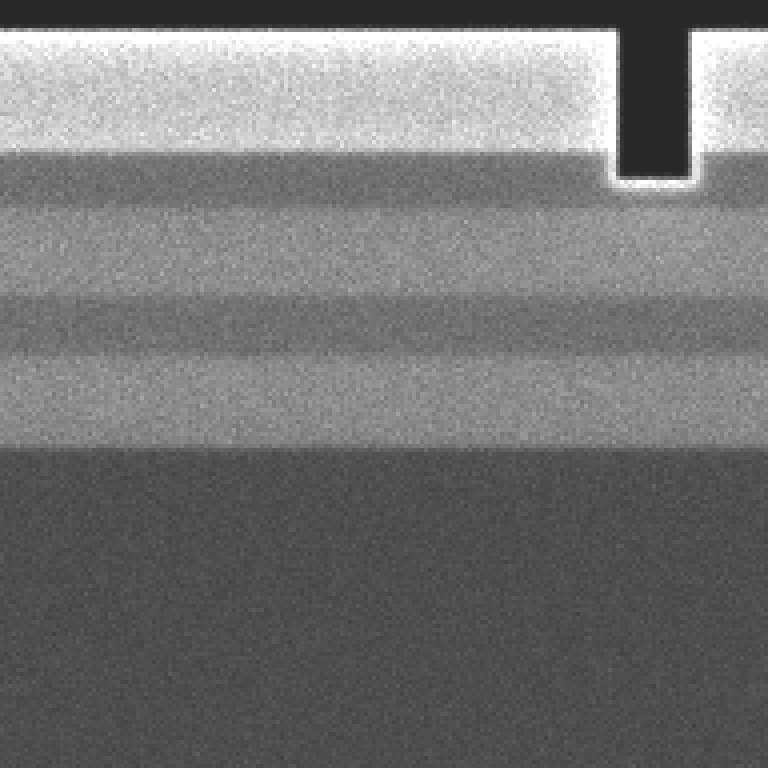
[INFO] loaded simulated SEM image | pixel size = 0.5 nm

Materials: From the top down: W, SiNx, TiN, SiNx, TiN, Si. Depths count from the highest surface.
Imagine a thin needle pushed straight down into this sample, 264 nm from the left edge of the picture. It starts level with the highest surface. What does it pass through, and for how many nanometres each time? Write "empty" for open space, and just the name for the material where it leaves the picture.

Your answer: W 60, SiNx 28, TiN 44, SiNx 30, TiN 46, Si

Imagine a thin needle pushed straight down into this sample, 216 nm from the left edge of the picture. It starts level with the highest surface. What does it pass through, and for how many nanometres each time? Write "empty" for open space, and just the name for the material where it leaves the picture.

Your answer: W 60, SiNx 28, TiN 44, SiNx 30, TiN 46, Si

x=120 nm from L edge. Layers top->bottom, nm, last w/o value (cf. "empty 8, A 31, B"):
W 60, SiNx 28, TiN 44, SiNx 30, TiN 46, Si